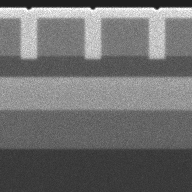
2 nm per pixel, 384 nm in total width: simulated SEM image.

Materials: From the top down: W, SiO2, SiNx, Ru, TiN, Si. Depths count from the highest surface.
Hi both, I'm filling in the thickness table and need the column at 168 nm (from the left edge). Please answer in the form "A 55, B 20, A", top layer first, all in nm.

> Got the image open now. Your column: W 20, SiO2 76, SiNx 42, Ru 66, TiN 78, Si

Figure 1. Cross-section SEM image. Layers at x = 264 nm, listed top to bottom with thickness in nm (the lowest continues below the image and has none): W 20, SiO2 76, SiNx 42, Ru 66, TiN 78, Si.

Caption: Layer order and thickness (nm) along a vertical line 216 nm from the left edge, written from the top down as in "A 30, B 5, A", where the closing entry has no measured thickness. W 20, SiO2 76, SiNx 42, Ru 66, TiN 78, Si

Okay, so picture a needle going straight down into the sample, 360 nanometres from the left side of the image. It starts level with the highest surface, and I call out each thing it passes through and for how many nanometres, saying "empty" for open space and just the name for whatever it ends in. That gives W 20, SiO2 76, SiNx 42, Ru 66, TiN 78, Si